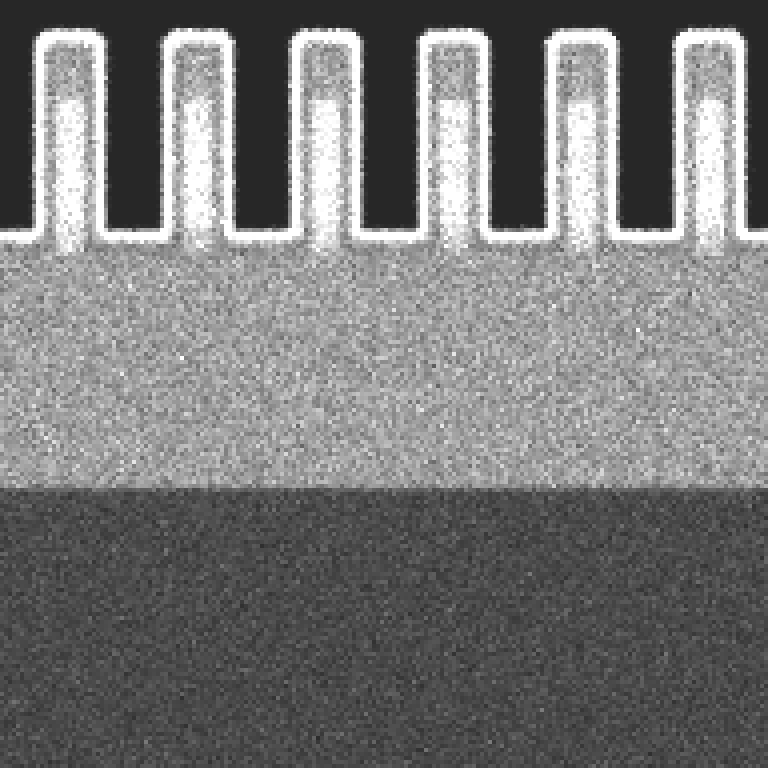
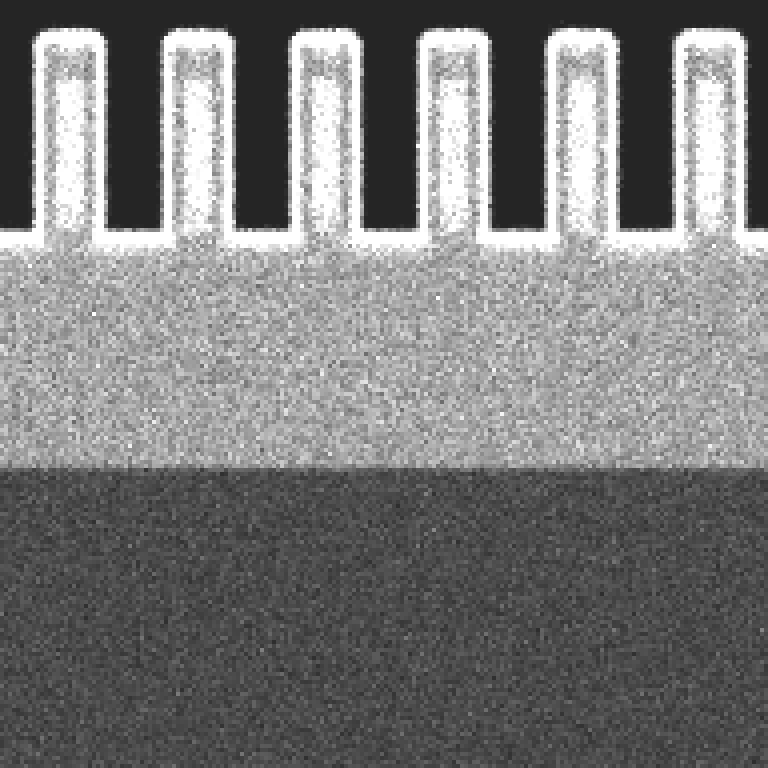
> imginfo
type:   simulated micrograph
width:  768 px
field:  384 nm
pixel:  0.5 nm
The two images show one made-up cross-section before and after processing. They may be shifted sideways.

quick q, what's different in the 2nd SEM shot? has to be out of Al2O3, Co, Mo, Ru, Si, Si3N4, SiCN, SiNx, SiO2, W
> Si3N4 removed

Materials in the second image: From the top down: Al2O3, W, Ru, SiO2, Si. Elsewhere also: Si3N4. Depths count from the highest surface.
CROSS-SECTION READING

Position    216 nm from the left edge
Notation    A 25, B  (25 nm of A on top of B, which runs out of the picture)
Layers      Si3N4 100, SiO2 118, Si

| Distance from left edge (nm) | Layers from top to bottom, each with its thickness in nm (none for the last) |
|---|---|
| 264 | empty 100, SiO2 118, Si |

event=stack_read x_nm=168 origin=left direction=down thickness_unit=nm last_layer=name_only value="Al2O3 24, W 62, Ru 14, SiO2 118, Si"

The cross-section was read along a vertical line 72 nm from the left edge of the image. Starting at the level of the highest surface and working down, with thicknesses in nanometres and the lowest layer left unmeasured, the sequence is empty 100, SiO2 118, Si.